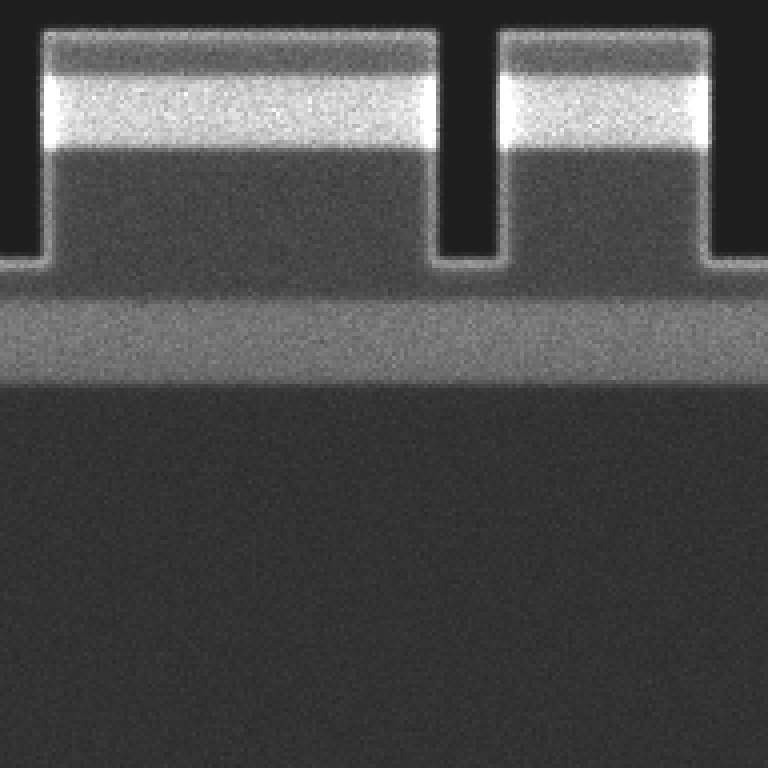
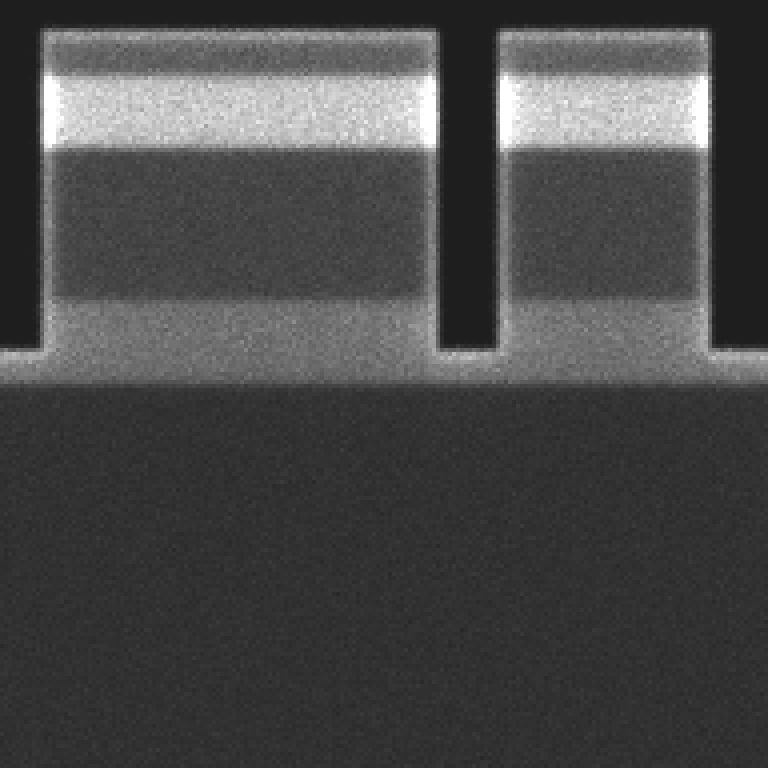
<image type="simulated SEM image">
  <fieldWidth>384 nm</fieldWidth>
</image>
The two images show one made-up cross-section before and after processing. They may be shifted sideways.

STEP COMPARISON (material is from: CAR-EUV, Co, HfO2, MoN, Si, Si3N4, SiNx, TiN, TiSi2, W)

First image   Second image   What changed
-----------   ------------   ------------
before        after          Co and SiNx, removed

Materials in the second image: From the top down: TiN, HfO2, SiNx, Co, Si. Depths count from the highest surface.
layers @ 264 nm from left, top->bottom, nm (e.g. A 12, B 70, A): TiN 22, HfO2 36, SiNx 76, Co 42, Si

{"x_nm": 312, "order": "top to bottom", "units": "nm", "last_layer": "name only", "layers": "TiN 22, HfO2 36, SiNx 76, Co 42, Si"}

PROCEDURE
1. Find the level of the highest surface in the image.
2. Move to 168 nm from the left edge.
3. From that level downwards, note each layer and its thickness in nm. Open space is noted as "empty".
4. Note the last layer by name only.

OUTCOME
TiN 22, HfO2 36, SiNx 76, Co 42, Si